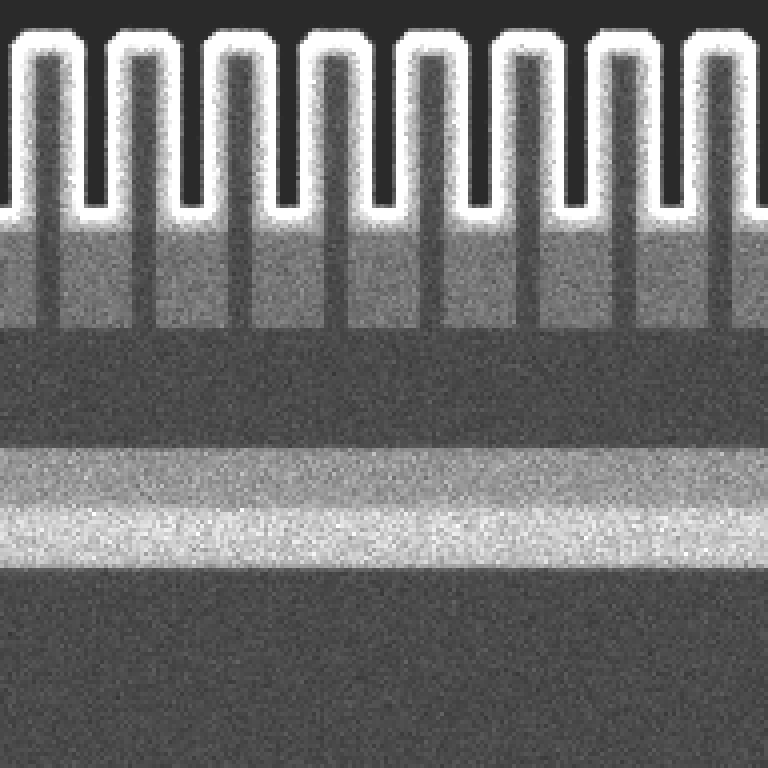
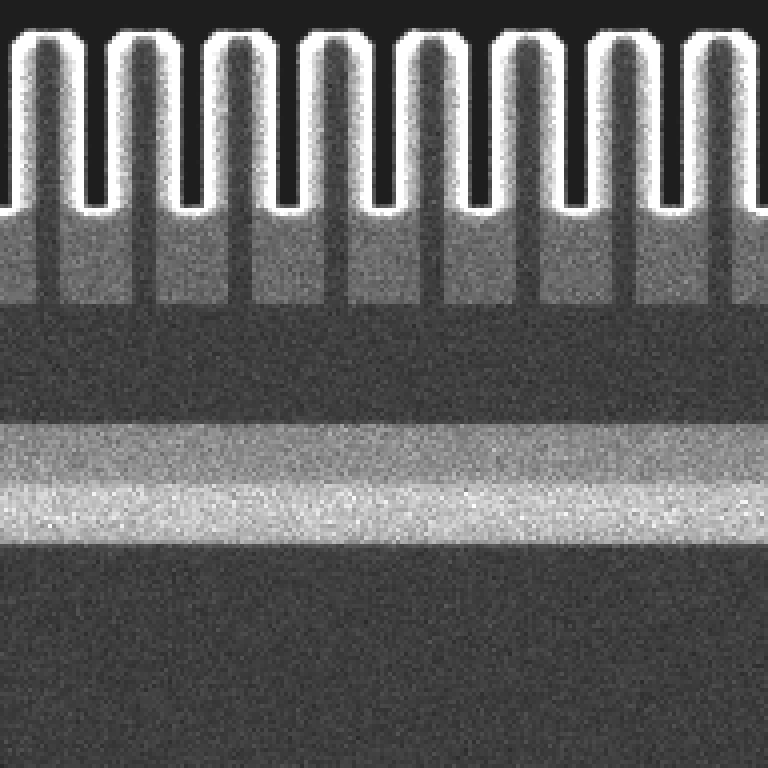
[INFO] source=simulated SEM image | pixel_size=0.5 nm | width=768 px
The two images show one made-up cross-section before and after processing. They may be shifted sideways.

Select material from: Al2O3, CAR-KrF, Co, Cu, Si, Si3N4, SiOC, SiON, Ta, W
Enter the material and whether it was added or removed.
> Al2O3 / removed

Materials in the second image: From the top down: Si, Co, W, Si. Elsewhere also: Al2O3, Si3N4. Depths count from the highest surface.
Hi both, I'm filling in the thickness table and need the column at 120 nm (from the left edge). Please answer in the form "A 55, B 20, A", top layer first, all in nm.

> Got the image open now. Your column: Si 196, Co 30, W 30, Si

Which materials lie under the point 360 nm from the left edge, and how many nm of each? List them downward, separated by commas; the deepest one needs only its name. Si 196, Co 30, W 30, Si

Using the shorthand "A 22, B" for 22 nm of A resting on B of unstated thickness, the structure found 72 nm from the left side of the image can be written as Si 196, Co 30, W 30, Si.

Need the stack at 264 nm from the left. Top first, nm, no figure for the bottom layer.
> Si 196, Co 30, W 30, Si